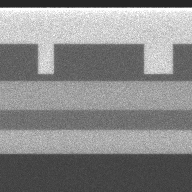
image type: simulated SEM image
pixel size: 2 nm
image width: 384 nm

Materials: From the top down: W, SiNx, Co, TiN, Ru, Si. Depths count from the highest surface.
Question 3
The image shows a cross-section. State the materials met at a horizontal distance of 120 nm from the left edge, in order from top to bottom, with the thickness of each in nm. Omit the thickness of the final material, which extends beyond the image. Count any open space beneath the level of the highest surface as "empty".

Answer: W 72, SiNx 74, Co 58, TiN 40, Ru 48, Si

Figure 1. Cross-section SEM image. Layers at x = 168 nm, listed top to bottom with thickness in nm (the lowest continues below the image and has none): W 72, SiNx 74, Co 58, TiN 40, Ru 48, Si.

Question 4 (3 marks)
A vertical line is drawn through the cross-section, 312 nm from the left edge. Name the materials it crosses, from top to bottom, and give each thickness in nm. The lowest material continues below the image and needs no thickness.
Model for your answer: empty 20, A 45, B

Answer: W 132, SiNx 14, Co 58, TiN 40, Ru 48, Si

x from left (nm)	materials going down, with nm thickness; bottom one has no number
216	W 72, SiNx 74, Co 58, TiN 40, Ru 48, Si